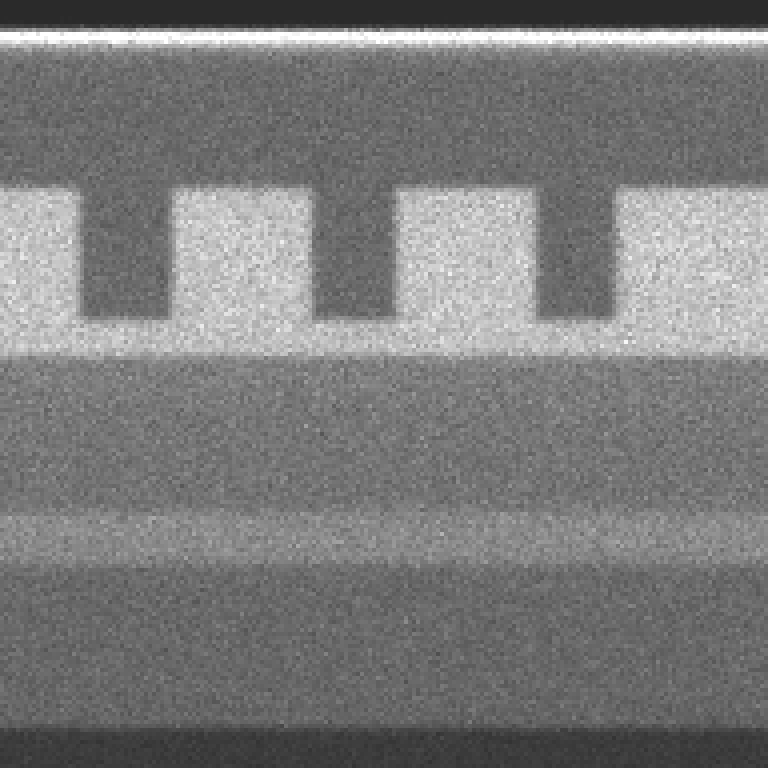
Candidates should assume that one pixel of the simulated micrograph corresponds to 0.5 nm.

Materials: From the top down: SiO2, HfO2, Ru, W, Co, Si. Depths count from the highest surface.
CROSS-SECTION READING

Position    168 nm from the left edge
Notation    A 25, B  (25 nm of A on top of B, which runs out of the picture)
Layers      SiO2 144, HfO2 18, Ru 78, W 26, Co 82, Si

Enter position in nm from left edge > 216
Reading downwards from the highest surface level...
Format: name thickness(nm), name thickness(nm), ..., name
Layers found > SiO2 78, HfO2 84, Ru 78, W 26, Co 82, Si